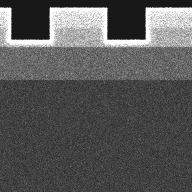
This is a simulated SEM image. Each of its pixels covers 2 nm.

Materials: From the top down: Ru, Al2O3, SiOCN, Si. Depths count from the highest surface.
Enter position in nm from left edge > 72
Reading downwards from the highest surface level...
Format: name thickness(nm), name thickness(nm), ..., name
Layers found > empty 64, Al2O3 14, SiOCN 66, Si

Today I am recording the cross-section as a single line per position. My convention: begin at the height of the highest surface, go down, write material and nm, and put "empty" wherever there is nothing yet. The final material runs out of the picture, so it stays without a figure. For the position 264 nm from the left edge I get empty 64, Al2O3 14, SiOCN 66, Si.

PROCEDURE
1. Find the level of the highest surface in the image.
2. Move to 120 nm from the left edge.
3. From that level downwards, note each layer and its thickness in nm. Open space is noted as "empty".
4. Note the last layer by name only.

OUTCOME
Ru 40, Al2O3 38, SiOCN 66, Si